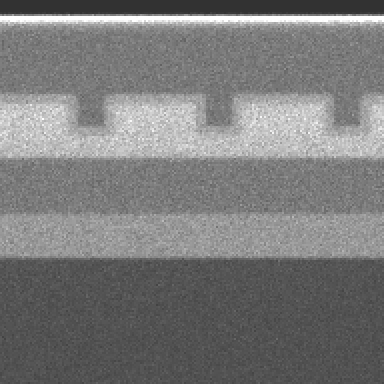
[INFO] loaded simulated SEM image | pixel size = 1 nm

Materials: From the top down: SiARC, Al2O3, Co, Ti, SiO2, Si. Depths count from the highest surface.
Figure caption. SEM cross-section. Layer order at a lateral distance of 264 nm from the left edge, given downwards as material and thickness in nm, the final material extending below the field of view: SiARC 78, Al2O3 10, Co 54, Ti 56, SiO2 44, Si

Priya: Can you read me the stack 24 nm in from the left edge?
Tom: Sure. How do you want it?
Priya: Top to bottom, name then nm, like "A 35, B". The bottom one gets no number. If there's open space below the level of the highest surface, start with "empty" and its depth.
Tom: SiARC 78, Al2O3 10, Co 54, Ti 56, SiO2 44, Si